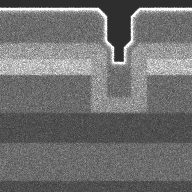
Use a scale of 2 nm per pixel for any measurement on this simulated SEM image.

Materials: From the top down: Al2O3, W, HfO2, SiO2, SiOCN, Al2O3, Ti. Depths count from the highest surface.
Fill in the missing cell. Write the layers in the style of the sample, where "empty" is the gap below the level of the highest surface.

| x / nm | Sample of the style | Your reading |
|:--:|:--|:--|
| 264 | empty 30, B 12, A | empty 14, Al2O3 70, W 126, SiOCN 60, Al2O3 76, Ti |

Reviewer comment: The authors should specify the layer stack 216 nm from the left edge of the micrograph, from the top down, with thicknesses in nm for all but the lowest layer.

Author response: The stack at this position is empty 68, Al2O3 110, W 32, SiOCN 60, Al2O3 76, Ti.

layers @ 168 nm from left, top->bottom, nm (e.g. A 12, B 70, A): Al2O3 70, W 32, HfO2 32, SiO2 76, SiOCN 60, Al2O3 76, Ti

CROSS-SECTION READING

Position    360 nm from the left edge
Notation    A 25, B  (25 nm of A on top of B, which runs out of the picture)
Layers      Al2O3 70, W 32, HfO2 32, SiO2 76, SiOCN 60, Al2O3 76, Ti